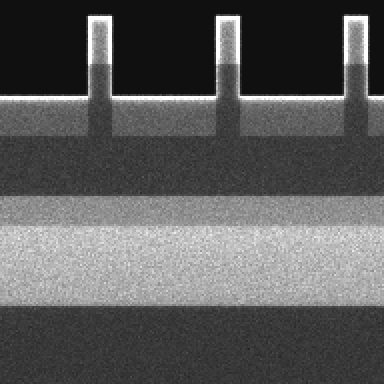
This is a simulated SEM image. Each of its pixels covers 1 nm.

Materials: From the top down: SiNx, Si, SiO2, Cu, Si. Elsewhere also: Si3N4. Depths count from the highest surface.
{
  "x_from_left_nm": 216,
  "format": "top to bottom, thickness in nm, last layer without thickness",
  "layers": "Si3N4 48, Si 132, SiO2 30, Cu 80, Si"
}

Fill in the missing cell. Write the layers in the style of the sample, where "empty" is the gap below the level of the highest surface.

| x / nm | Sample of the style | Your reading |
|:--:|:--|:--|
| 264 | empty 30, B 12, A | empty 80, SiNx 40, Si 60, SiO2 30, Cu 80, Si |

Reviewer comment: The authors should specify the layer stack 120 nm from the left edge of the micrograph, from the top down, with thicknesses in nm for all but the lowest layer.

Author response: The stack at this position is empty 80, SiNx 40, Si 60, SiO2 30, Cu 80, Si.